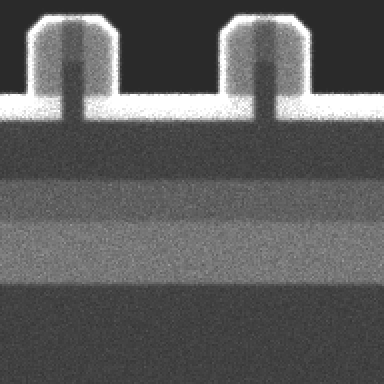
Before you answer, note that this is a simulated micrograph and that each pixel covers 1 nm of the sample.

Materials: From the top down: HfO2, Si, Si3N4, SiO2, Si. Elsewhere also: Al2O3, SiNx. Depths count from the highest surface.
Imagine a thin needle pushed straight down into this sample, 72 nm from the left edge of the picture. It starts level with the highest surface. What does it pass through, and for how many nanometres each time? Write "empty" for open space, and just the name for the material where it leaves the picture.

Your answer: SiNx 46, Si 118, Si3N4 42, SiO2 62, Si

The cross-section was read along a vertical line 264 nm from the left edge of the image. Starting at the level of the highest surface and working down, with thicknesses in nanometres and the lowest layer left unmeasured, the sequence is SiNx 46, Si 118, Si3N4 42, SiO2 62, Si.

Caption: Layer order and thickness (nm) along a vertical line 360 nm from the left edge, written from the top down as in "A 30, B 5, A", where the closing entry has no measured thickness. empty 80, HfO2 24, Si 60, Si3N4 42, SiO2 62, Si